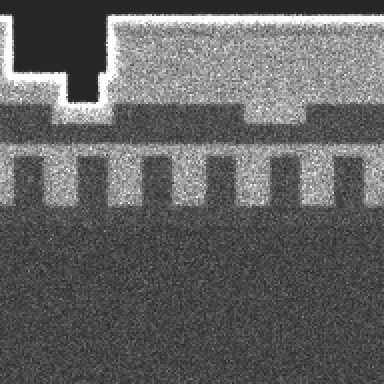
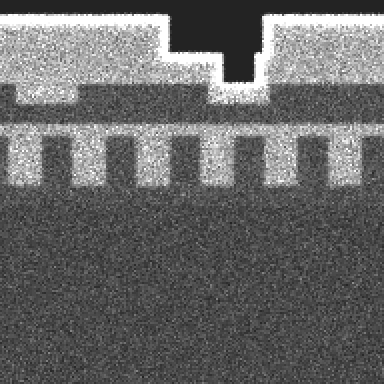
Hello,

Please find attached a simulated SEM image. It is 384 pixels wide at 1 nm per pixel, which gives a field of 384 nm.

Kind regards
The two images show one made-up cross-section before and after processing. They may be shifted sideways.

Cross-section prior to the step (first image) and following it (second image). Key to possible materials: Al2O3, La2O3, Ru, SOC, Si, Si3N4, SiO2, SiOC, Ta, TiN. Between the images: SOC was removed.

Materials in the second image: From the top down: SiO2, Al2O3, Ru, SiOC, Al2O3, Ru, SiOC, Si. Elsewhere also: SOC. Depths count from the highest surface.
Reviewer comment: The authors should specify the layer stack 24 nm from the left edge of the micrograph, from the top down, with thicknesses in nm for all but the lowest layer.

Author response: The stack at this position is SiO2 58, Al2O3 10, Ru 20, SiOC 20, Al2O3 12, Ru 50, SiOC 20, Si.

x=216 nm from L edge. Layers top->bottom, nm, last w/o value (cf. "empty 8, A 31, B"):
empty 38, SiO2 20, Al2O3 10, Ru 20, SiOC 20, Al2O3 12, Ru 50, SiOC 20, Si